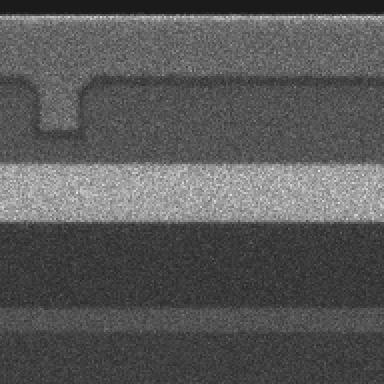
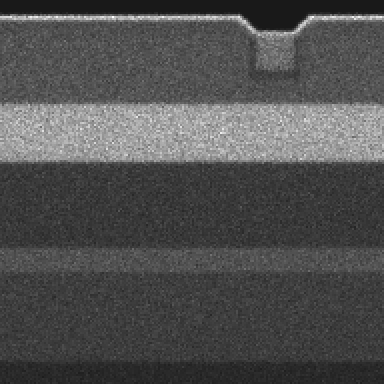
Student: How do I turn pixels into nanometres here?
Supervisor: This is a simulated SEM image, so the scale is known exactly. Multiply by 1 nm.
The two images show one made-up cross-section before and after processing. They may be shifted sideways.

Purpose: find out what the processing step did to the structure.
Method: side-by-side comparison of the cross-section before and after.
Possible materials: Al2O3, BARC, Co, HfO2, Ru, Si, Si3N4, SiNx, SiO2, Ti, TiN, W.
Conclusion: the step removed Ru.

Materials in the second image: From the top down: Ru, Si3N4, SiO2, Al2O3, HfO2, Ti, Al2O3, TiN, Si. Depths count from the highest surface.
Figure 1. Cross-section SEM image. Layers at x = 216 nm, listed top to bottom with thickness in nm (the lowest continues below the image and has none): Si3N4 10, SiO2 12, Al2O3 66, HfO2 58, Ti 86, Al2O3 24, TiN 90, Si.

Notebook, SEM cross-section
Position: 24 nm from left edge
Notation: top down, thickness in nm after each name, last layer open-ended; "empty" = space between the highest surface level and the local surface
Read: Si3N4 10, SiO2 12, Al2O3 66, HfO2 58, Ti 86, Al2O3 24, TiN 90, Si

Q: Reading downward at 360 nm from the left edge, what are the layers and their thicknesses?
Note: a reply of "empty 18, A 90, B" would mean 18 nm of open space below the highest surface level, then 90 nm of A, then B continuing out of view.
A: Si3N4 10, SiO2 12, Al2O3 66, HfO2 58, Ti 86, Al2O3 24, TiN 90, Si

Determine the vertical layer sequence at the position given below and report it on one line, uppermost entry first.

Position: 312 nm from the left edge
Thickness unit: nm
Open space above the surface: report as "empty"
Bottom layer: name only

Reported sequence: Si3N4 10, SiO2 12, Al2O3 66, HfO2 58, Ti 86, Al2O3 24, TiN 90, Si